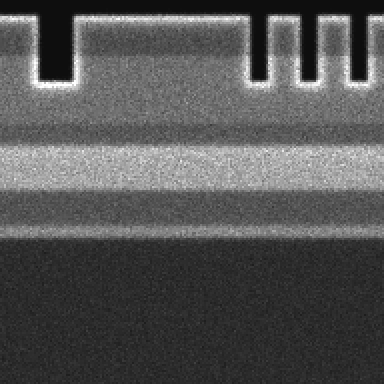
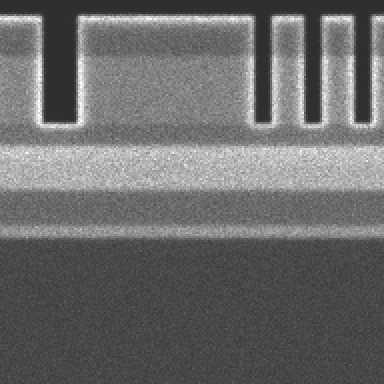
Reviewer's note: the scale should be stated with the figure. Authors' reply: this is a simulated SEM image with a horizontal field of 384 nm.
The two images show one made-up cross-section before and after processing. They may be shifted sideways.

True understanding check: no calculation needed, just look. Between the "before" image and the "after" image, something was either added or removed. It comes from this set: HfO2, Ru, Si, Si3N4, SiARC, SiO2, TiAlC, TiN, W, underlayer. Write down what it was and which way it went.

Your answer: SiO2 (removed)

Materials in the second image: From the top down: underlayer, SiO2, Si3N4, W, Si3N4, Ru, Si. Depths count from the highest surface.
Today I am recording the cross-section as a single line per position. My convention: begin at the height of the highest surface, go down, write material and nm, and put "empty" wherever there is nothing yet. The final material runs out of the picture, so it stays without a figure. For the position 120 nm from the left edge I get underlayer 40, SiO2 68, Si3N4 22, W 44, Si3N4 36, Ru 12, Si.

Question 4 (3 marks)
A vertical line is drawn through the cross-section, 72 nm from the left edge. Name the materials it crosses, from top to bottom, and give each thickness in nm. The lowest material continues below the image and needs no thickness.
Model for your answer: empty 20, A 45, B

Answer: empty 108, Si3N4 22, W 44, Si3N4 36, Ru 12, Si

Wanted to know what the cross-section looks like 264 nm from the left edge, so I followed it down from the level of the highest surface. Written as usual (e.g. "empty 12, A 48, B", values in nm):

empty 108, Si3N4 22, W 44, Si3N4 36, Ru 12, Si